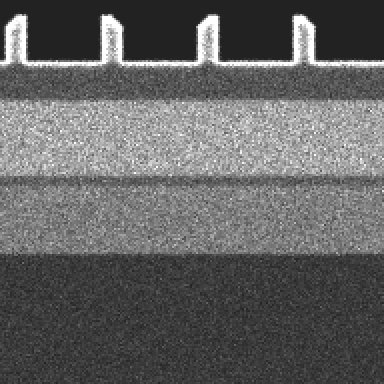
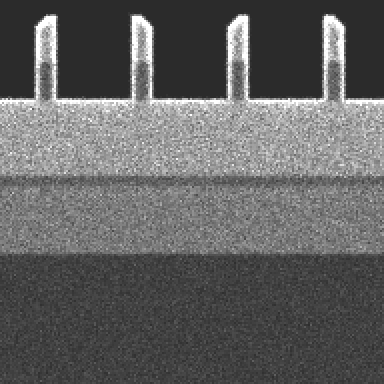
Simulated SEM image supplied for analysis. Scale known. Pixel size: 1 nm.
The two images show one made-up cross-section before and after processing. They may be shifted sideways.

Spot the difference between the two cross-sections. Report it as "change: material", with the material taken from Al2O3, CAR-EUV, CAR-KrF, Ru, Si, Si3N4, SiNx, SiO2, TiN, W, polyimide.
removed: SiNx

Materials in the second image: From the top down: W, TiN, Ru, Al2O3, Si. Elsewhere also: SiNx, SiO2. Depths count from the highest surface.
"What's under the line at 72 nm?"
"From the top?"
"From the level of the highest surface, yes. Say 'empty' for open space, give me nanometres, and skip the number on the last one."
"empty 84, W 76, TiN 10, Ru 12, Al2O3 56, Si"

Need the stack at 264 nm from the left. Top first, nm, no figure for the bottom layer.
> empty 84, W 76, TiN 10, Ru 12, Al2O3 56, Si